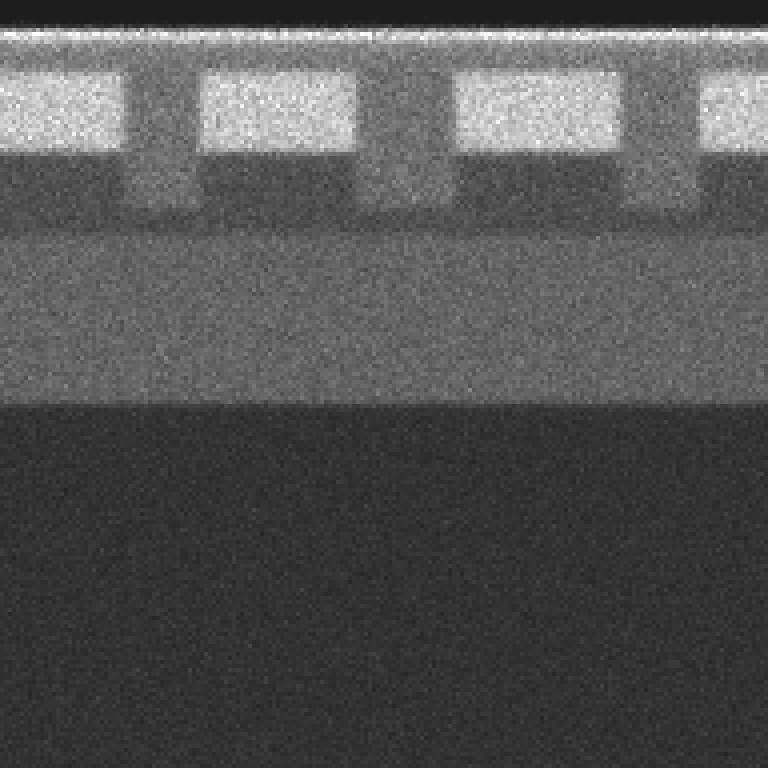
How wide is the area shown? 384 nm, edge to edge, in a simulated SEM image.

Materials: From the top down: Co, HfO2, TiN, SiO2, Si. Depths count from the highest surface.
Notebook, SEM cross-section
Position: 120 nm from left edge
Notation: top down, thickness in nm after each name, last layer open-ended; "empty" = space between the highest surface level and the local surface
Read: Co 20, HfO2 40, TiN 42, SiO2 84, Si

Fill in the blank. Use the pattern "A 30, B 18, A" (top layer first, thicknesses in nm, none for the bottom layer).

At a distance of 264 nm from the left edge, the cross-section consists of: Co 20, HfO2 40, TiN 42, SiO2 84, Si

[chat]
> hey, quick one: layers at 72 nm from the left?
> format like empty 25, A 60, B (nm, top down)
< Co 88, TiN 14, SiO2 84, Si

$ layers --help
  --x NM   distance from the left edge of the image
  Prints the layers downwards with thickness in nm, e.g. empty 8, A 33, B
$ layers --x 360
Co 20, HfO2 40, TiN 42, SiO2 84, Si